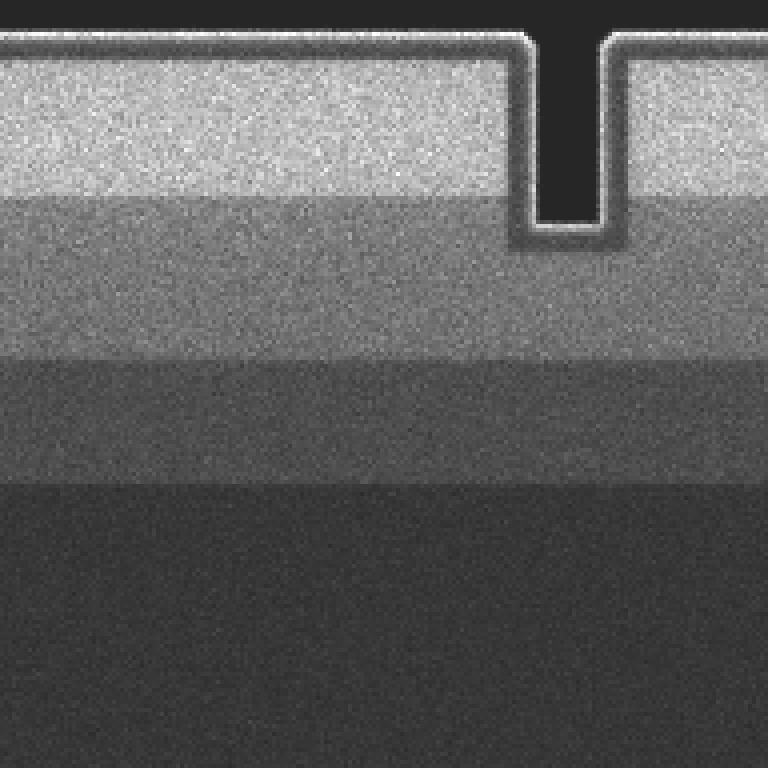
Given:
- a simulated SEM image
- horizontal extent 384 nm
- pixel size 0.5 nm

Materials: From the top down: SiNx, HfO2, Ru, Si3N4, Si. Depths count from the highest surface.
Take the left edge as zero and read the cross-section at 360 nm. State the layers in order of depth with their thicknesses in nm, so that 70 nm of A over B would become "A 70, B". SiNx 14, HfO2 68, Ru 82, Si3N4 62, Si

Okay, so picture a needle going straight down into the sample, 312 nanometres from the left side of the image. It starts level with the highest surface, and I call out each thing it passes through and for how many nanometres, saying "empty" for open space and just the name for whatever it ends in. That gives SiNx 110, Ru 54, Si3N4 62, Si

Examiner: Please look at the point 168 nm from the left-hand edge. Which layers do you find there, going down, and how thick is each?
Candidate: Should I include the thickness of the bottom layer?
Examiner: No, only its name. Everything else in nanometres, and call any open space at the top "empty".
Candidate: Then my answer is SiNx 14, HfO2 68, Ru 82, Si3N4 62, Si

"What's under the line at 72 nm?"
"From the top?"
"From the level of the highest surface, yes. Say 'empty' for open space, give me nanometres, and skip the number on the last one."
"SiNx 14, HfO2 68, Ru 82, Si3N4 62, Si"